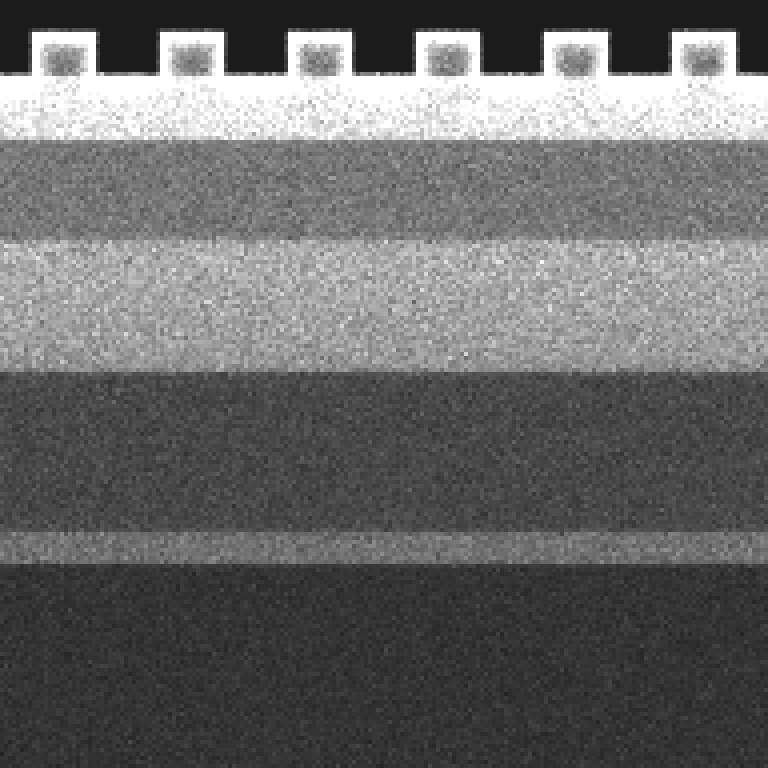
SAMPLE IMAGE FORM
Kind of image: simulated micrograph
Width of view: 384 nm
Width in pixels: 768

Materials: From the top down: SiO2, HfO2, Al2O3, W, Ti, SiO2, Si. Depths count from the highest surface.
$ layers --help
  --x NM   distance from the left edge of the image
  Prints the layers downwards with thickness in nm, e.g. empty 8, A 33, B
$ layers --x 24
SiO2 22, HfO2 32, Al2O3 50, W 66, Ti 80, SiO2 16, Si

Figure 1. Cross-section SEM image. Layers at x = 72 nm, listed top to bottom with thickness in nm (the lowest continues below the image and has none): empty 22, HfO2 32, Al2O3 50, W 66, Ti 80, SiO2 16, Si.